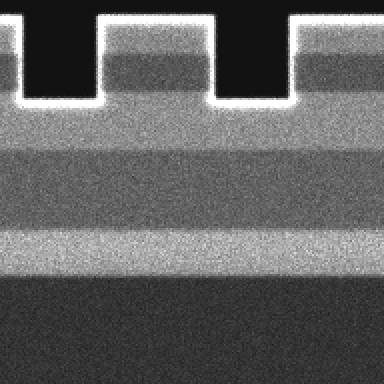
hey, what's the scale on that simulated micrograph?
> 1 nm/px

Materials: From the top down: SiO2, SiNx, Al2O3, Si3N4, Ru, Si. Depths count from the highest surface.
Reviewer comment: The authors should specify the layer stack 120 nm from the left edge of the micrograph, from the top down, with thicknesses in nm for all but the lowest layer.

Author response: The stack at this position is SiO2 38, SiNx 38, Al2O3 58, Si3N4 80, Ru 46, Si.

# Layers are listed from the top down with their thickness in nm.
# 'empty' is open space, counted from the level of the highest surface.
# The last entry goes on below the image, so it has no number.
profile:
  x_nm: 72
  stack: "empty 84, Al2O3 50, Si3N4 80, Ru 46, Si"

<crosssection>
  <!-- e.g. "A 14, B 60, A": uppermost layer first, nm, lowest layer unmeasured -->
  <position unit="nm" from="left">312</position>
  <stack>SiO2 38, SiNx 38, Al2O3 58, Si3N4 80, Ru 46, Si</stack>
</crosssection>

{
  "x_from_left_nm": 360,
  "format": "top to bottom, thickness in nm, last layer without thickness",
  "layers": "SiO2 38, SiNx 38, Al2O3 58, Si3N4 80, Ru 46, Si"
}